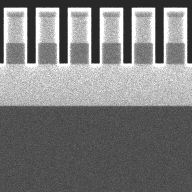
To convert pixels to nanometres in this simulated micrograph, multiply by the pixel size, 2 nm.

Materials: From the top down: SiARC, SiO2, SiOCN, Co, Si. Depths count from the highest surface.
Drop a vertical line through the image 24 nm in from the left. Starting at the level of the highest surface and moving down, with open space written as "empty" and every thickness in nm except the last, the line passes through SiARC 18, SiO2 52, SiOCN 42, Co 84, Si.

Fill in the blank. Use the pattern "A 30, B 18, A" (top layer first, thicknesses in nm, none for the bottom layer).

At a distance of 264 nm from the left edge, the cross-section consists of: SiARC 18, SiO2 52, SiOCN 42, Co 84, Si